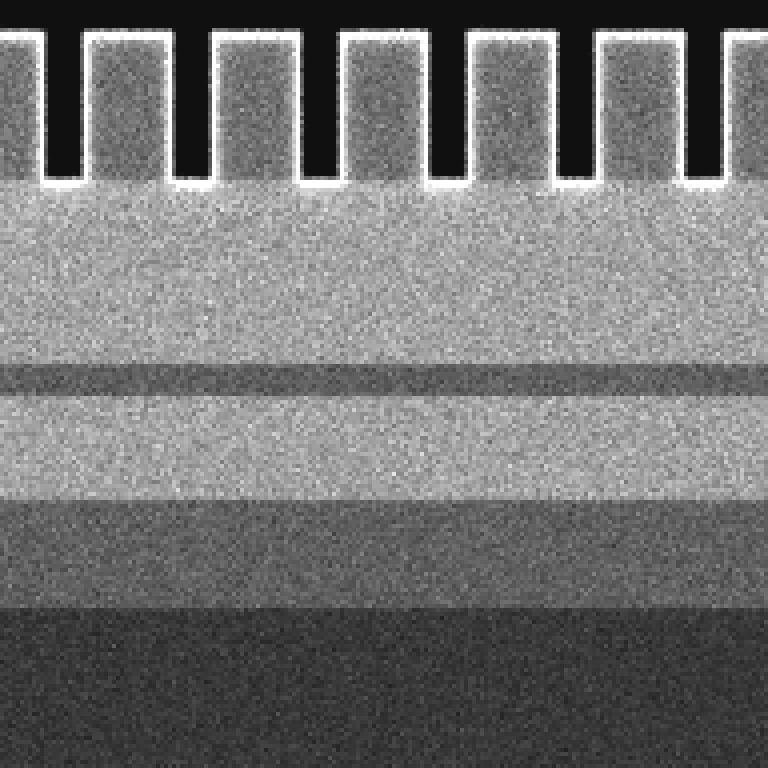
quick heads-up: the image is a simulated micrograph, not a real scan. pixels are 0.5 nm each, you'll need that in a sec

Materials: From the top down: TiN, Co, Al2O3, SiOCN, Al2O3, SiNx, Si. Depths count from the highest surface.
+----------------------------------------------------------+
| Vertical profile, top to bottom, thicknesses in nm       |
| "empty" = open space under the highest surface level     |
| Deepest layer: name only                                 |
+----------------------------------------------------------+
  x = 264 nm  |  TiN 74, Co 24, Al2O3 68, SiOCN 16, Al2O3 52, SiNx 54, Si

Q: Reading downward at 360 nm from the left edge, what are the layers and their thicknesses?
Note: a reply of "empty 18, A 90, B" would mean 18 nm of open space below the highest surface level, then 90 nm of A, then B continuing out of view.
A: empty 74, Co 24, Al2O3 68, SiOCN 16, Al2O3 52, SiNx 54, Si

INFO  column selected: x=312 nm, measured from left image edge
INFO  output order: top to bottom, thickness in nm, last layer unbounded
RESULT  TiN 74, Co 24, Al2O3 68, SiOCN 16, Al2O3 52, SiNx 54, Si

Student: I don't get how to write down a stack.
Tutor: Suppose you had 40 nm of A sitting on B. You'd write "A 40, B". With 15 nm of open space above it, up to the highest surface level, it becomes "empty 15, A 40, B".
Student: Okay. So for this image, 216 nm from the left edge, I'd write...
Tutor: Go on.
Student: empty 74, Co 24, Al2O3 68, SiOCN 16, Al2O3 52, SiNx 54, Si